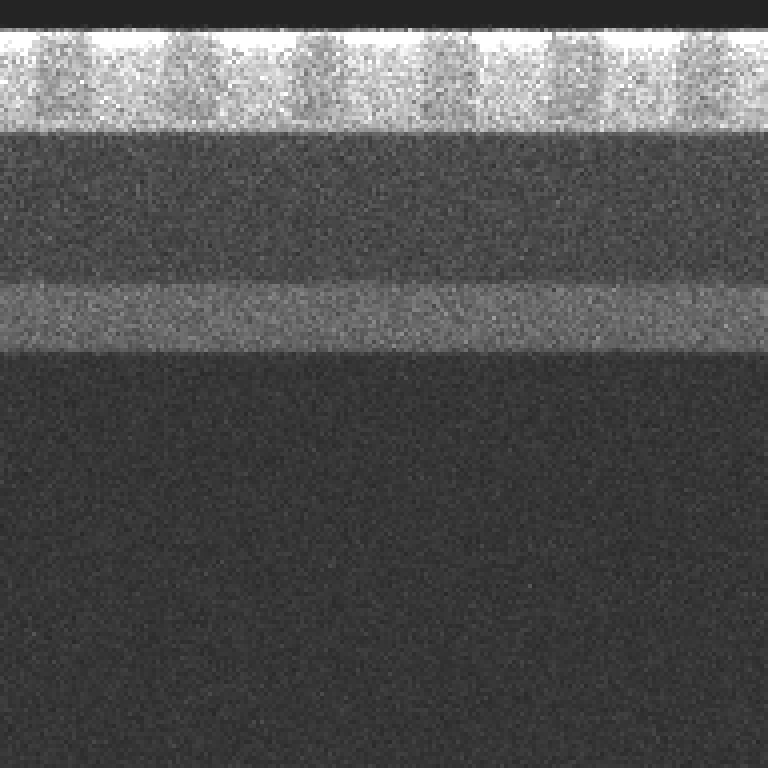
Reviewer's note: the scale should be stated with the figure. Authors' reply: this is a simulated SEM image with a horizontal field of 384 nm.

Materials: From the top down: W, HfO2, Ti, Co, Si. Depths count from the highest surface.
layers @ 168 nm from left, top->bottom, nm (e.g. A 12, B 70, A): W 44, HfO2 6, Ti 76, Co 34, Si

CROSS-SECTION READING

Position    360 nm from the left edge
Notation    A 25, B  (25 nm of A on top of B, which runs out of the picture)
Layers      W 44, HfO2 6, Ti 76, Co 34, Si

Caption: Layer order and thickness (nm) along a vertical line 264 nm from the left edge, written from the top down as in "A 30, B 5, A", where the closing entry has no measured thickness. HfO2 50, Ti 76, Co 34, Si